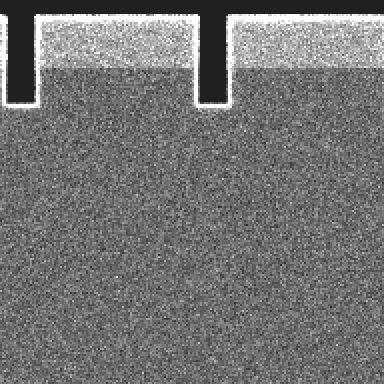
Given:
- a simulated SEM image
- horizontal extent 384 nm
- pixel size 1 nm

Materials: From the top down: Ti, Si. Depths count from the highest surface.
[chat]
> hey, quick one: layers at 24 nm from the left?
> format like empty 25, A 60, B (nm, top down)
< empty 88, Si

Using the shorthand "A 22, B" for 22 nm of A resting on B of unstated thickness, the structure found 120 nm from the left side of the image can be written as Ti 52, Si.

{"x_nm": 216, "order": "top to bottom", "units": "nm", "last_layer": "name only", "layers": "empty 88, Si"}